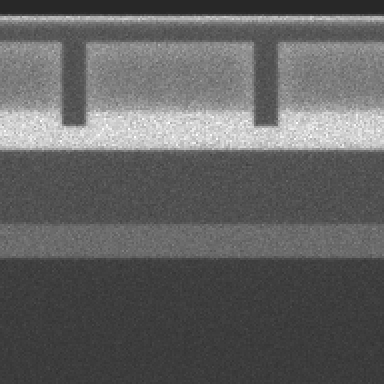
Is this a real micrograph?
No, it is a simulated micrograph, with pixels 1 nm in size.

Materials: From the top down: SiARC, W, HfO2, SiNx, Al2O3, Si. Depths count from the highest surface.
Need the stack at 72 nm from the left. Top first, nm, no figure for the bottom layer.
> SiARC 110, HfO2 24, SiNx 74, Al2O3 34, Si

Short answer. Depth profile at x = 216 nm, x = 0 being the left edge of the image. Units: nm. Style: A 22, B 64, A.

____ SiARC 26, W 70, HfO2 38, SiNx 74, Al2O3 34, Si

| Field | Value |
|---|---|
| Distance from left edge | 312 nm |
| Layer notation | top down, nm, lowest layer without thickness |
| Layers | SiARC 26, W 70, HfO2 38, SiNx 74, Al2O3 34, Si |